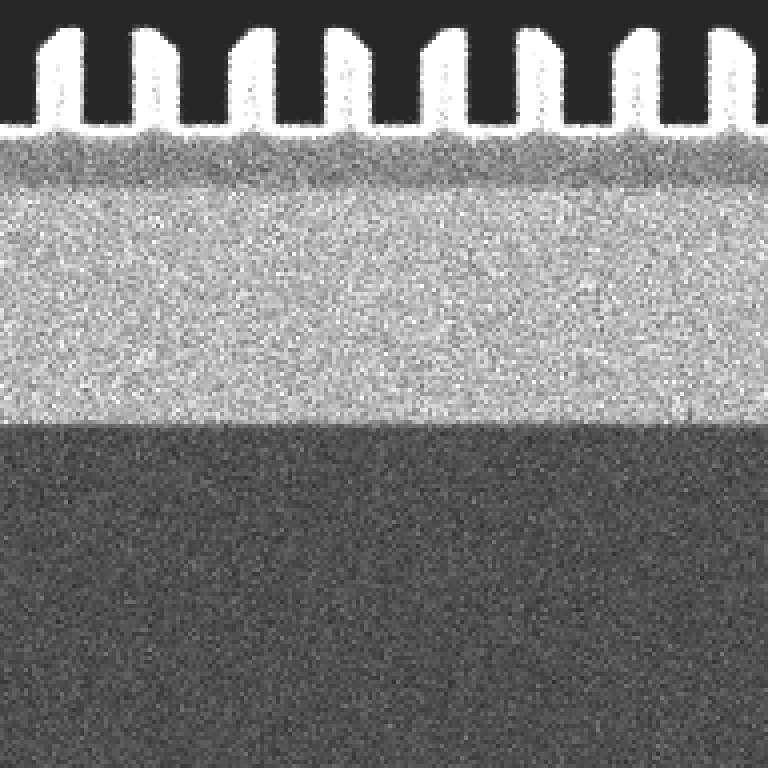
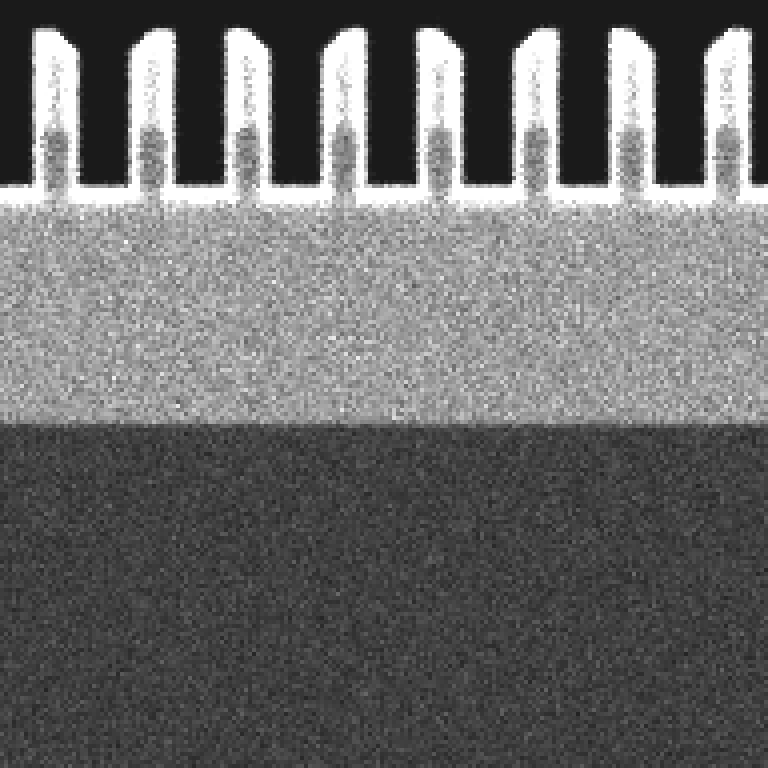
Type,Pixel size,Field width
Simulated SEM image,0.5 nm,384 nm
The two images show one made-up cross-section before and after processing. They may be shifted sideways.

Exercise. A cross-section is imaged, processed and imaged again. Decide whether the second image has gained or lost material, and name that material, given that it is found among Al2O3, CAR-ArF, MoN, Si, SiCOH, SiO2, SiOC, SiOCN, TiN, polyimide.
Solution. removed: TiN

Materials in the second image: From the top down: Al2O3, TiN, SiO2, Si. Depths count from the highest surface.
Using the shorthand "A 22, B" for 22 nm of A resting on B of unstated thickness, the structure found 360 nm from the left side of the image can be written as empty 4, Al2O3 44, TiN 30, SiO2 118, Si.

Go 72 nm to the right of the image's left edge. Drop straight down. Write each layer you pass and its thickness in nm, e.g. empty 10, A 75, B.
empty 4, Al2O3 44, TiN 30, SiO2 118, Si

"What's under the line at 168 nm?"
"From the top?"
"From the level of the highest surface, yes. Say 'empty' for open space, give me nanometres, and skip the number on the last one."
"empty 4, Al2O3 44, TiN 30, SiO2 118, Si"